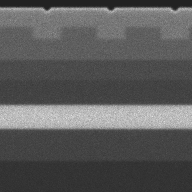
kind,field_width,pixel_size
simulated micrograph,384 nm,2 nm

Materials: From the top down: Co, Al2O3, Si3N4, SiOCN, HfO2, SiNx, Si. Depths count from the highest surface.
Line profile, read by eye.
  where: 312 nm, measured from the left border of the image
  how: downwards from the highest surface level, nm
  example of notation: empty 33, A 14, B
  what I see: Co 38, Al2O3 66, Si3N4 40, SiOCN 50, HfO2 48, SiNx 64, Si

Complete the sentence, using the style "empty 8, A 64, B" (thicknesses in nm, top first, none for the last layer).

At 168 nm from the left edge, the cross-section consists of Co 38, Al2O3 66, Si3N4 40, SiOCN 50, HfO2 48, SiNx 64, Si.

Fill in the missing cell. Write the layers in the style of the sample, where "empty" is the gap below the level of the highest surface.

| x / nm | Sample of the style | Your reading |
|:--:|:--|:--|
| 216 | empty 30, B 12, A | empty 4, Co 58, Al2O3 42, Si3N4 40, SiOCN 50, HfO2 48, SiNx 64, Si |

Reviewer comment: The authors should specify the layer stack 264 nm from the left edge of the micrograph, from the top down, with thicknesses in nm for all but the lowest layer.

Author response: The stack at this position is Co 38, Al2O3 66, Si3N4 40, SiOCN 50, HfO2 48, SiNx 64, Si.